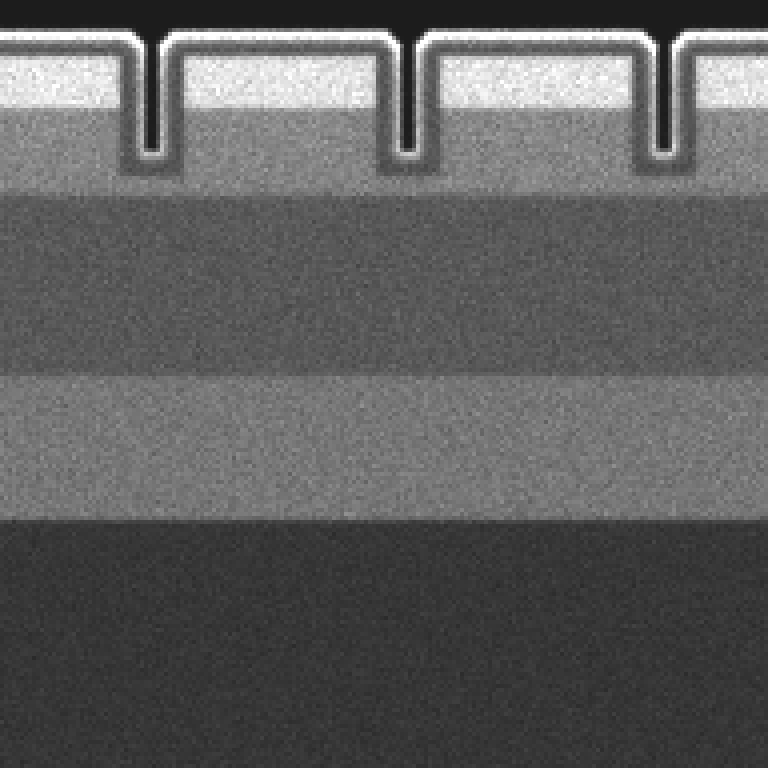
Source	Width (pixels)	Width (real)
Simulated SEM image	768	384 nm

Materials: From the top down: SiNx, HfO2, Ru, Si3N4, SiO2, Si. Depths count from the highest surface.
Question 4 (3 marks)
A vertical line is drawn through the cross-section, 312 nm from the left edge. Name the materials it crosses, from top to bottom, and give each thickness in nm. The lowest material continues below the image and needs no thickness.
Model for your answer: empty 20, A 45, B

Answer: SiNx 12, HfO2 26, Ru 44, Si3N4 90, SiO2 72, Si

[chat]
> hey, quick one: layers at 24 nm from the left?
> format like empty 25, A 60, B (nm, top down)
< SiNx 12, HfO2 26, Ru 44, Si3N4 90, SiO2 72, Si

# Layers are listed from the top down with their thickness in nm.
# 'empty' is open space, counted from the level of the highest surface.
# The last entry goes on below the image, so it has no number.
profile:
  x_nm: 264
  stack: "SiNx 12, HfO2 26, Ru 44, Si3N4 90, SiO2 72, Si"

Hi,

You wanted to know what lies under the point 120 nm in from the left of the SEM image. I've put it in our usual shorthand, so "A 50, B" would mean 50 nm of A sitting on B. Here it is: SiNx 12, HfO2 26, Ru 44, Si3N4 90, SiO2 72, Si